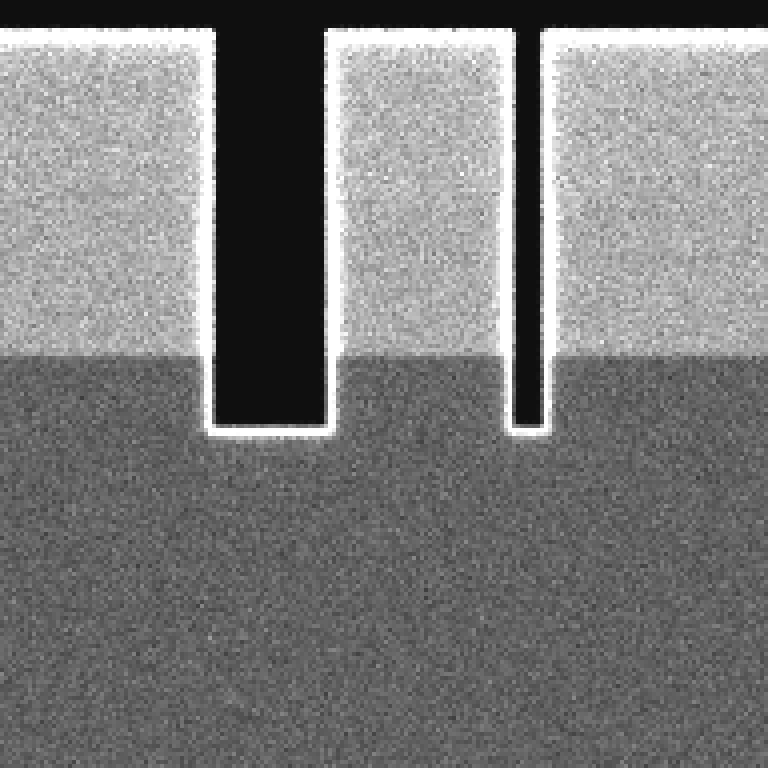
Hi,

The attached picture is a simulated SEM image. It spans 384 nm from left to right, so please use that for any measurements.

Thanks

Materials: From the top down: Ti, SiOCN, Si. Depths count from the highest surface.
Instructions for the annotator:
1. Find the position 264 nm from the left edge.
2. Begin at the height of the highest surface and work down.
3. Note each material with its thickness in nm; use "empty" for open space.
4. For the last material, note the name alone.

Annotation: empty 198, Si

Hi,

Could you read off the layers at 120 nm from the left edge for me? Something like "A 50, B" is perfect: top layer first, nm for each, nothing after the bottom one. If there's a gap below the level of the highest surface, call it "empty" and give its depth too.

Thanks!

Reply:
empty 198, Si